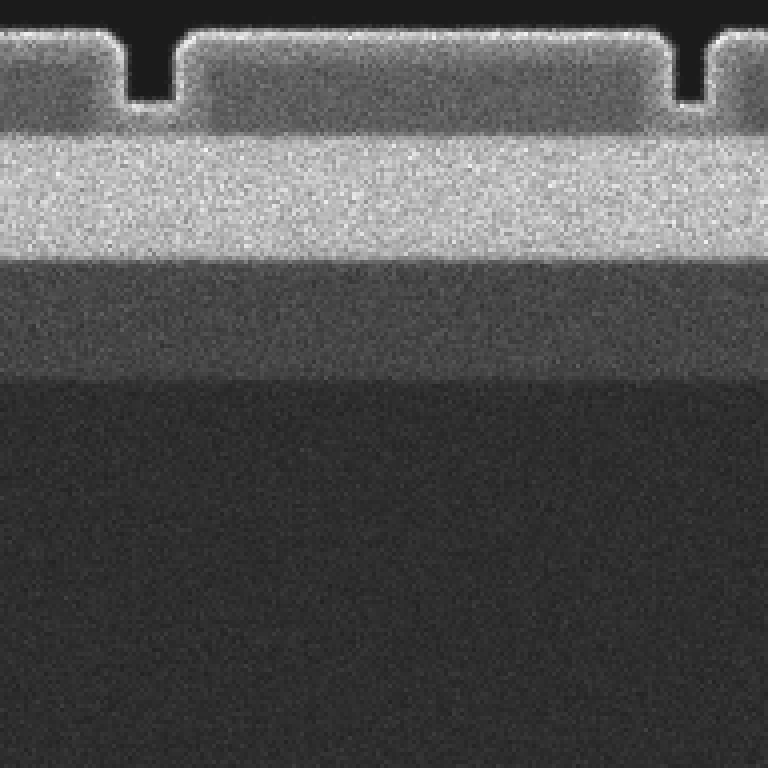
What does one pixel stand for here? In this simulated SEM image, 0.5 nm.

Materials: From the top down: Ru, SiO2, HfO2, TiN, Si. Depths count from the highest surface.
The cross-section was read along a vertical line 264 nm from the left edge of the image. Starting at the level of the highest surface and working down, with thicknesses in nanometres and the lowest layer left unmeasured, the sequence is Ru 16, SiO2 36, HfO2 62, TiN 60, Si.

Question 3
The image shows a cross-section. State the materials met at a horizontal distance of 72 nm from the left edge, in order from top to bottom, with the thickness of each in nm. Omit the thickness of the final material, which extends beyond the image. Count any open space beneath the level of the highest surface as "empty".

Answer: empty 36, Ru 16, HfO2 62, TiN 60, Si